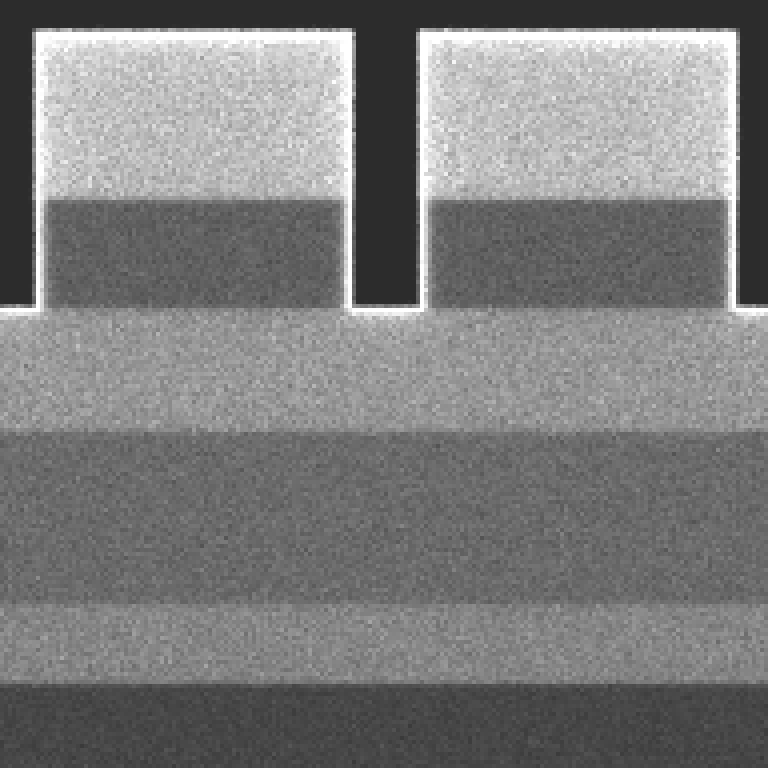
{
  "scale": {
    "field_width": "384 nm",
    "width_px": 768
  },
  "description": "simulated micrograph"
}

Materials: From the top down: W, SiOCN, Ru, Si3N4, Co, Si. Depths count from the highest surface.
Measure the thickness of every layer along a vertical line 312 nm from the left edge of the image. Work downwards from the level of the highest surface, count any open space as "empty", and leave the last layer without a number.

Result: W 84, SiOCN 54, Ru 62, Si3N4 86, Co 40, Si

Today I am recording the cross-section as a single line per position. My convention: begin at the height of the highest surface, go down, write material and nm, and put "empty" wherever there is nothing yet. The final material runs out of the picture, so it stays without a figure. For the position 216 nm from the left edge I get W 84, SiOCN 54, Ru 62, Si3N4 86, Co 40, Si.